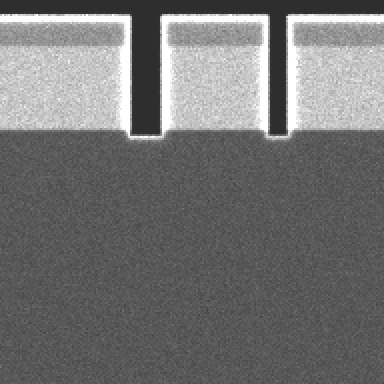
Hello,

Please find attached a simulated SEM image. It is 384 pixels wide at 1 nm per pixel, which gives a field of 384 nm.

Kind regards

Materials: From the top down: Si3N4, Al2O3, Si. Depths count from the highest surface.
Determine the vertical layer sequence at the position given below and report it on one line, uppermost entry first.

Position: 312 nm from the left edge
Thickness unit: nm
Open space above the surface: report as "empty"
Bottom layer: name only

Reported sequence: Si3N4 30, Al2O3 84, Si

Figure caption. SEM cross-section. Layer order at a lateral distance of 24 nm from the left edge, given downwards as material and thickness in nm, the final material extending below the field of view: Si3N4 30, Al2O3 84, Si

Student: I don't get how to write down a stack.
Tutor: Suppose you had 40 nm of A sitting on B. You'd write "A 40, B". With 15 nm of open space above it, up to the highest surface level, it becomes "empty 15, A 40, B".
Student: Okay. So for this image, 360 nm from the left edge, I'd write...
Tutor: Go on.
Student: Si3N4 30, Al2O3 84, Si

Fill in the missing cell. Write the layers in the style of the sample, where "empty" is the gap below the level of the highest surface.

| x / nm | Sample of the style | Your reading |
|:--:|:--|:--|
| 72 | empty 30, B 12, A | Si3N4 30, Al2O3 84, Si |